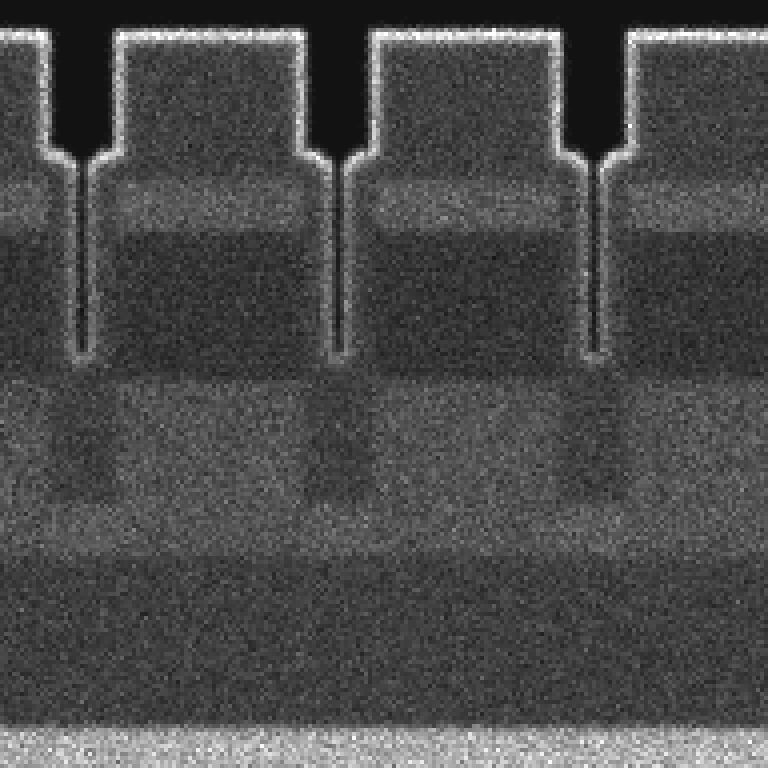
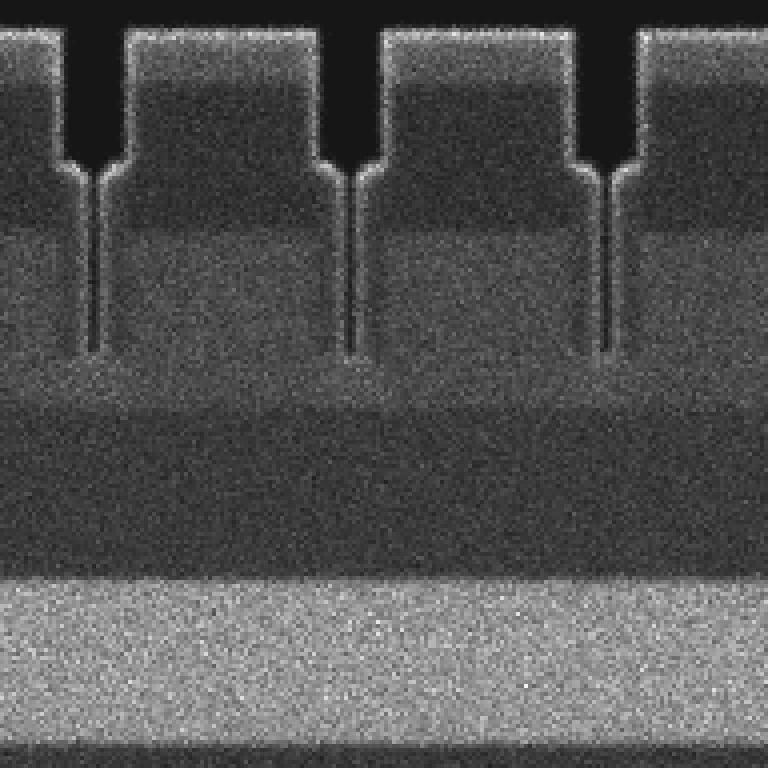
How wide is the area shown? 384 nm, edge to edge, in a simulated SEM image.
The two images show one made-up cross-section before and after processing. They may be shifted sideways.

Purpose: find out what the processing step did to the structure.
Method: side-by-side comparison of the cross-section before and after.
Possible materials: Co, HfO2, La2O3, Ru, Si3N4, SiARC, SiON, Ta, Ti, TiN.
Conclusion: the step removed Si3N4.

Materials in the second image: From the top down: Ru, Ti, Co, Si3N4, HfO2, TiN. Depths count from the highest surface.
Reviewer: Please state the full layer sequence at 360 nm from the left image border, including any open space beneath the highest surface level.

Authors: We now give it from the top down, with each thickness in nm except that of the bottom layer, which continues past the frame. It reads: Ru 26, Ti 74, Co 88, Si3N4 86, HfO2 82, TiN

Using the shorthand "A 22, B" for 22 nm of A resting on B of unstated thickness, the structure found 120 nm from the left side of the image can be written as Ru 26, Ti 74, Co 88, Si3N4 86, HfO2 82, TiN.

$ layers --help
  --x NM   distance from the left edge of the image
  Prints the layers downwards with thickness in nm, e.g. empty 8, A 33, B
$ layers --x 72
Ru 26, Ti 74, Co 88, Si3N4 86, HfO2 82, TiN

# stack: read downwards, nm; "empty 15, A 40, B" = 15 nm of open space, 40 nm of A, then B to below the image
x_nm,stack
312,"empty 66, Si3N4 96, Ru 26, Si3N4 86, HfO2 82, TiN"